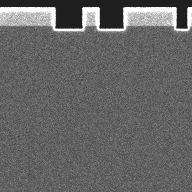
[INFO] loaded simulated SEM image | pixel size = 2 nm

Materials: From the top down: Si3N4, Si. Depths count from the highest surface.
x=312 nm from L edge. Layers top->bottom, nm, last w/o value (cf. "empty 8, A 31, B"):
Si3N4 36, Si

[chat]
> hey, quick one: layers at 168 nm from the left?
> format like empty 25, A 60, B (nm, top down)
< Si3N4 36, Si